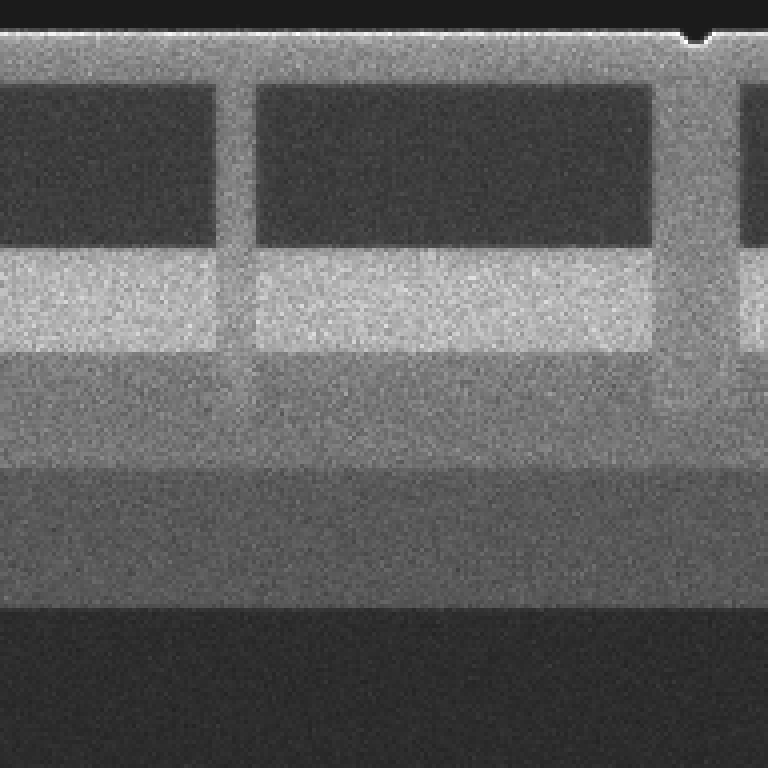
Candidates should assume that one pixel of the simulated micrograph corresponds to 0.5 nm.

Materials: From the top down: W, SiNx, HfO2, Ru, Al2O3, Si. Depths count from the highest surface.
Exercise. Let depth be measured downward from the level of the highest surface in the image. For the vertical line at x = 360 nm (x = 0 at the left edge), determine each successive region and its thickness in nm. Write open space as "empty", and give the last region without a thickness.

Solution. W 190, Ru 28, Al2O3 70, Si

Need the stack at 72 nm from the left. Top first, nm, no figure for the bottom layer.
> W 26, SiNx 82, HfO2 52, Ru 58, Al2O3 70, Si